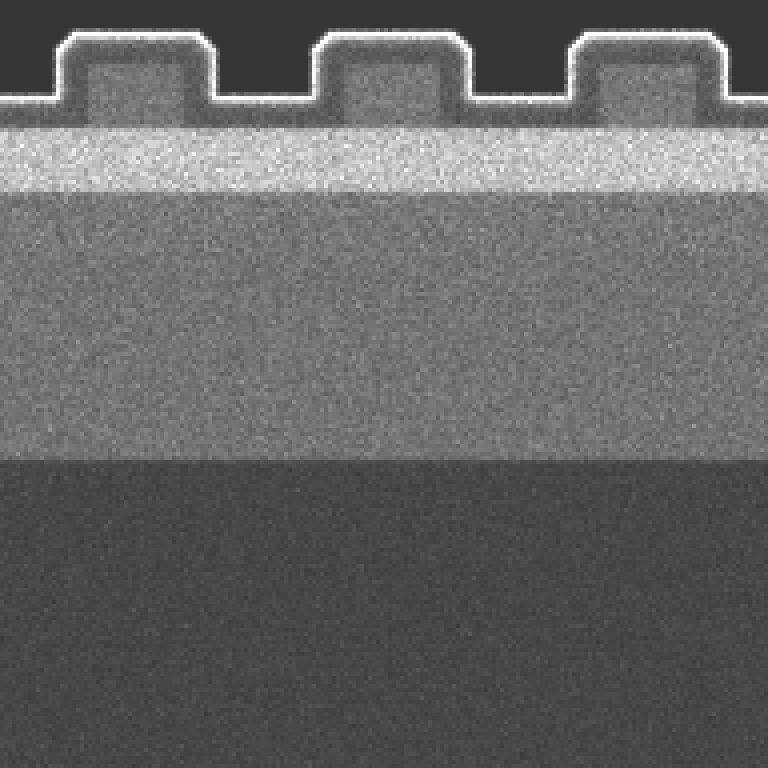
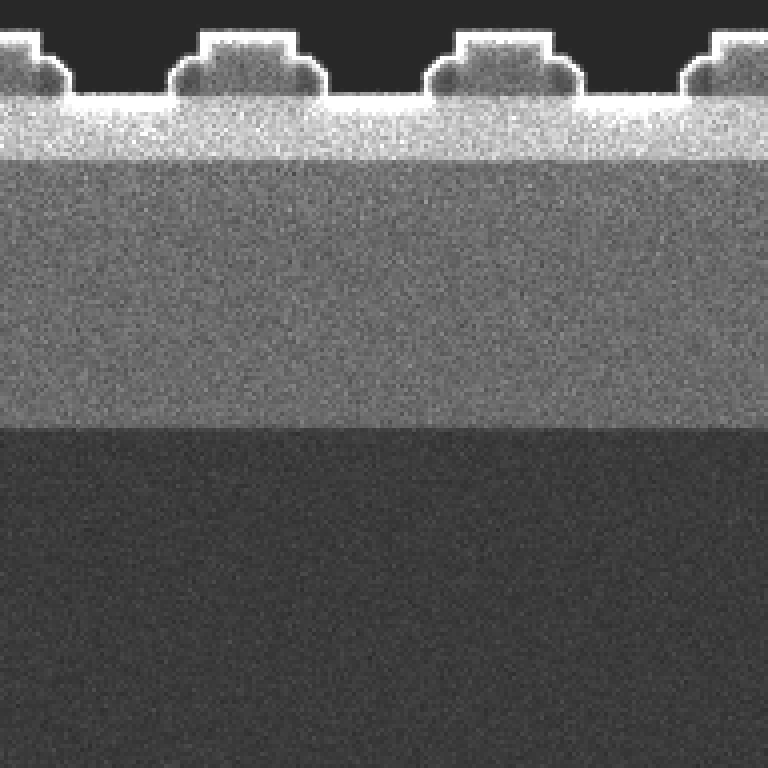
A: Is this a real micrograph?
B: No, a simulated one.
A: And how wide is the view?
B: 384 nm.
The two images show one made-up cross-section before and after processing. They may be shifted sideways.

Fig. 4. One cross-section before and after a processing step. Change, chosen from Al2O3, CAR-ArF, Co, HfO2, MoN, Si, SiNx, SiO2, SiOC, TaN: SiNx removed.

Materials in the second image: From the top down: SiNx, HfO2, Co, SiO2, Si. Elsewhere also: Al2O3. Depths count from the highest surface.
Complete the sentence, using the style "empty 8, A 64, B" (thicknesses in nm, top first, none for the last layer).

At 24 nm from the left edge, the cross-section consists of empty 12, SiNx 20, HfO2 32, Co 32, SiO2 102, Si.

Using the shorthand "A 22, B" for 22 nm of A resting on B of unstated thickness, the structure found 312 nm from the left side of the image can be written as empty 32, HfO2 32, Co 32, SiO2 102, Si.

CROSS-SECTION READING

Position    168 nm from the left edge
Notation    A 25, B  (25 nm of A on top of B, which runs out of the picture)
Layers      empty 32, HfO2 32, Co 32, SiO2 102, Si